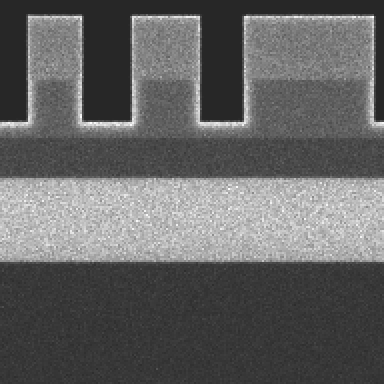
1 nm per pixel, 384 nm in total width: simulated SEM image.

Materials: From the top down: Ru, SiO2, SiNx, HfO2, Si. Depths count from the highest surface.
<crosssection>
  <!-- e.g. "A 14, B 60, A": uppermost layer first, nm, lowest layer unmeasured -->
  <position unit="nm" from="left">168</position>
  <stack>Ru 64, SiO2 58, SiNx 40, HfO2 84, Si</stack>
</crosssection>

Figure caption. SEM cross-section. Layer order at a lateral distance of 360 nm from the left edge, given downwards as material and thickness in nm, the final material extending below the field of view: Ru 64, SiO2 58, SiNx 40, HfO2 84, Si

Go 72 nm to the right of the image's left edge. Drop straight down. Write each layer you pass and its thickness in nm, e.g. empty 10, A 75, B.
Ru 64, SiO2 58, SiNx 40, HfO2 84, Si